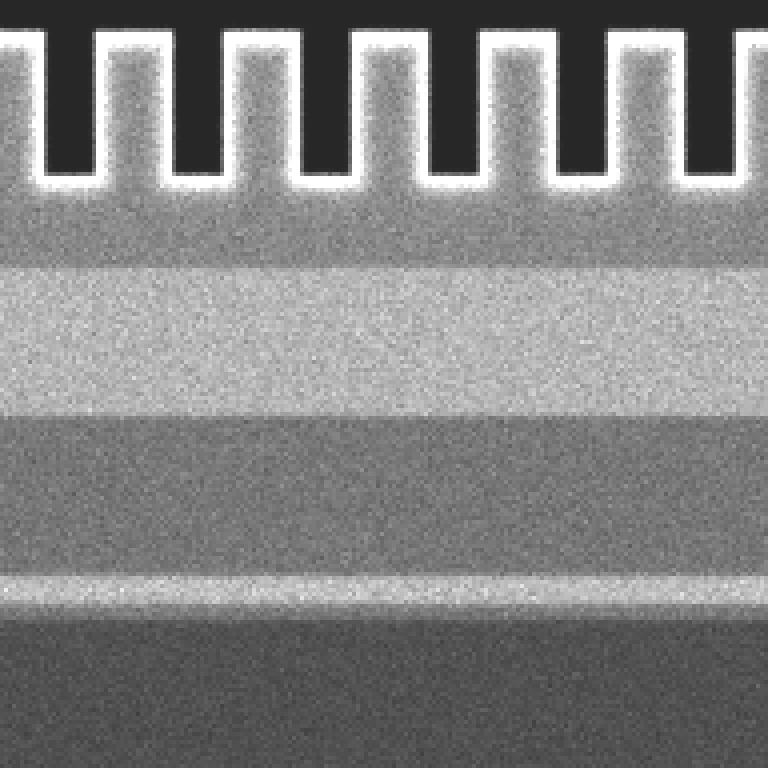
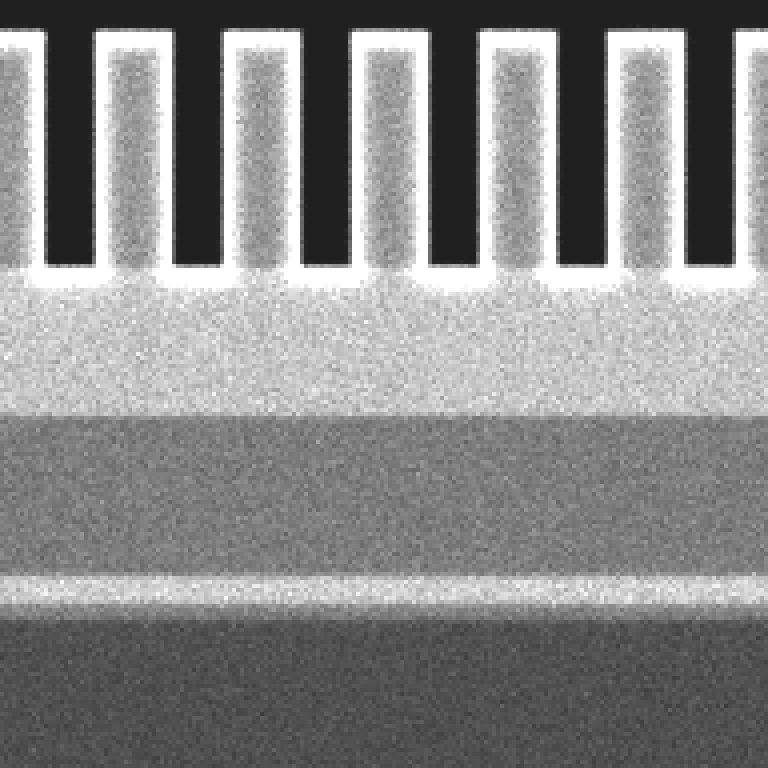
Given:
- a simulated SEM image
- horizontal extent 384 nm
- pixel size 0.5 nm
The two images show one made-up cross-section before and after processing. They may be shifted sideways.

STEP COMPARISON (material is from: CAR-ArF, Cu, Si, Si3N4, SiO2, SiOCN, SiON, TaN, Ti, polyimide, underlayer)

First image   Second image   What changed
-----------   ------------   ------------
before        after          underlayer, removed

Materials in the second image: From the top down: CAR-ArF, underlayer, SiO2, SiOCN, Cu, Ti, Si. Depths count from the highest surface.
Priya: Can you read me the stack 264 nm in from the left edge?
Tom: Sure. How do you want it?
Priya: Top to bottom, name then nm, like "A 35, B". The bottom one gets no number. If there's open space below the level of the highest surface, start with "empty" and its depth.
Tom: CAR-ArF 72, underlayer 46, SiO2 74, SiOCN 80, Cu 14, Ti 8, Si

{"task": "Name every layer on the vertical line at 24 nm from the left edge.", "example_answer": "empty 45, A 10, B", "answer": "empty 118, SiO2 74, SiOCN 80, Cu 14, Ti 8, Si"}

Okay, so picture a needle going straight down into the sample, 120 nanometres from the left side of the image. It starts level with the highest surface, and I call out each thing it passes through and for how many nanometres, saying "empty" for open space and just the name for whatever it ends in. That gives CAR-ArF 72, underlayer 46, SiO2 74, SiOCN 80, Cu 14, Ti 8, Si